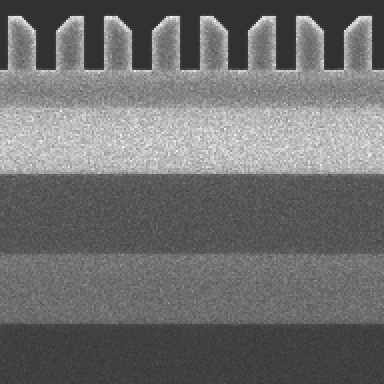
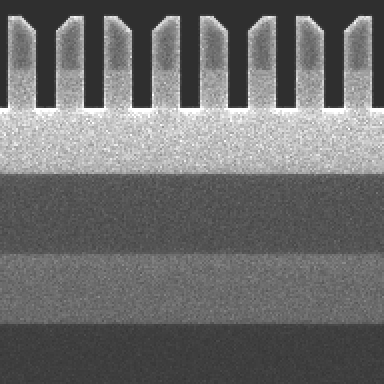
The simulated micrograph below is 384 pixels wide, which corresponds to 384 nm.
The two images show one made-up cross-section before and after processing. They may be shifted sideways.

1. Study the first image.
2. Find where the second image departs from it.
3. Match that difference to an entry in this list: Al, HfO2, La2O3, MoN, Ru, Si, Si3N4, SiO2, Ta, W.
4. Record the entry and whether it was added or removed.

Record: W / removed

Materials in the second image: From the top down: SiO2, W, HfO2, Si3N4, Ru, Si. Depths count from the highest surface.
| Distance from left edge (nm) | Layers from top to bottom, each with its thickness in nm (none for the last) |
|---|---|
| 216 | empty 4, SiO2 50, W 38, HfO2 66, Si3N4 80, Ru 70, Si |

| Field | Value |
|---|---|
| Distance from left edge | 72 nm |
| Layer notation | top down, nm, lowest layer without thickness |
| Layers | SiO2 54, W 38, HfO2 66, Si3N4 80, Ru 70, Si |